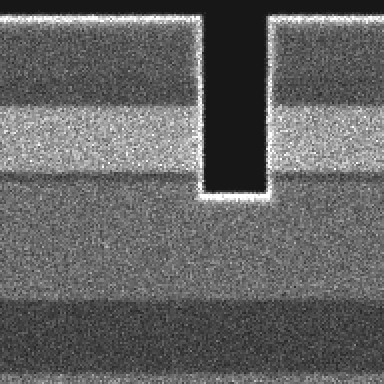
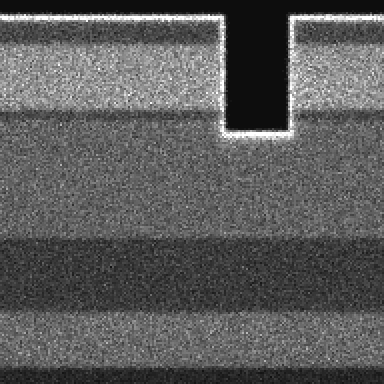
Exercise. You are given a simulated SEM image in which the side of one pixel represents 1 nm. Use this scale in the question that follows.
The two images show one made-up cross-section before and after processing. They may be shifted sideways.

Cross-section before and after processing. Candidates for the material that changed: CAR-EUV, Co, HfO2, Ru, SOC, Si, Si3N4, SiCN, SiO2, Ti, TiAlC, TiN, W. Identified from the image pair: SOC (removed).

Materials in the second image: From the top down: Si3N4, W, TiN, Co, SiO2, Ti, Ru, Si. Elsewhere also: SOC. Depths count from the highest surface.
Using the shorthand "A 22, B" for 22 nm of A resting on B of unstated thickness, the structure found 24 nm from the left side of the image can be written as Si3N4 28, W 66, TiN 10, Co 12, SiO2 106, Ti 74, Ru 56, Si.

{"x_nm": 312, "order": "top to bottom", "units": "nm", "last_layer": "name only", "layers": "Si3N4 28, W 66, TiN 10, Co 12, SiO2 106, Ti 74, Ru 56, Si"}